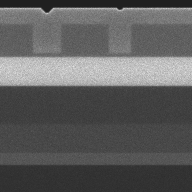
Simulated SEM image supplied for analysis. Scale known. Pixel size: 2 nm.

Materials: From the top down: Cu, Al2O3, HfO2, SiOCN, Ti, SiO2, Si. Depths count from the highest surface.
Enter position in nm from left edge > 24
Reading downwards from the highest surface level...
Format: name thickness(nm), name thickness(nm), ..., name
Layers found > Cu 32, Al2O3 66, HfO2 58, SiOCN 76, Ti 58, SiO2 24, Si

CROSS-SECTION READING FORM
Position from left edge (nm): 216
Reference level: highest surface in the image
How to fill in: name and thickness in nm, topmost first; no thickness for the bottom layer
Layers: Cu 32, Al2O3 66, HfO2 58, SiOCN 76, Ti 58, SiO2 24, Si